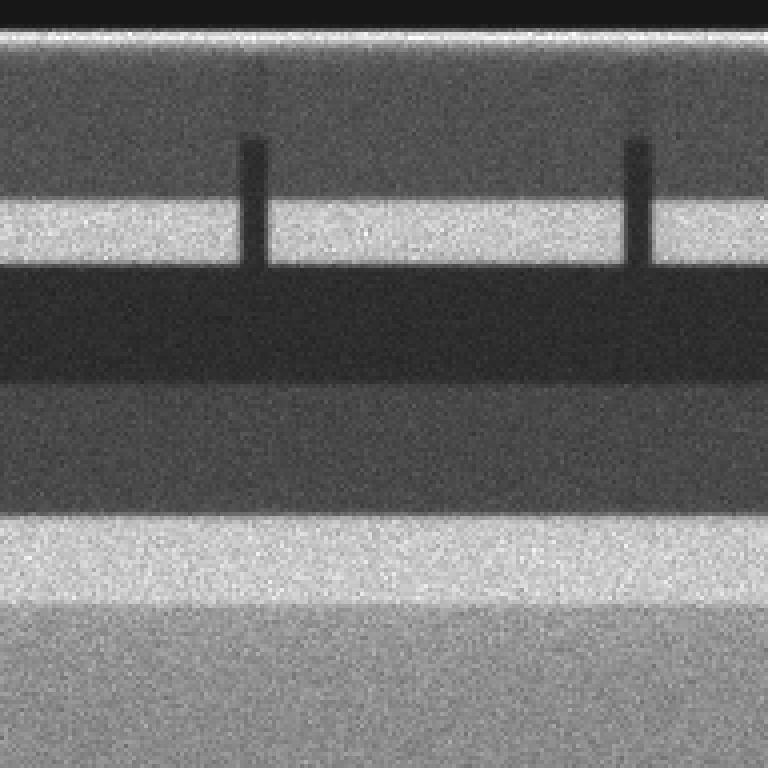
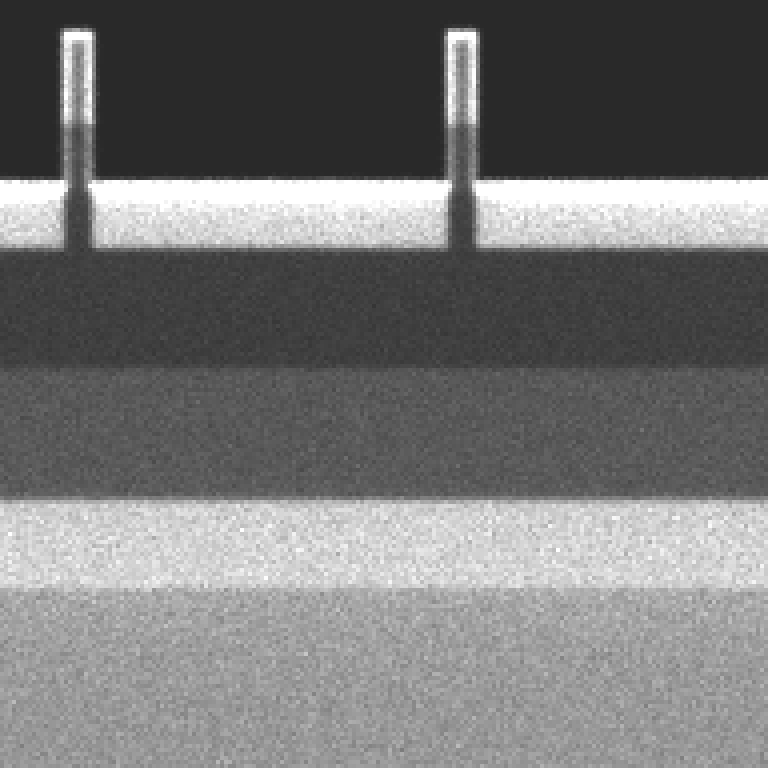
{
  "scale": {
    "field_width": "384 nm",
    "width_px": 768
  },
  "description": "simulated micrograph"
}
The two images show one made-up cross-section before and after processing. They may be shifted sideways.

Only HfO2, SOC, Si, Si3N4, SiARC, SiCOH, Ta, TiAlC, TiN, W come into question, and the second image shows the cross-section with SOC removed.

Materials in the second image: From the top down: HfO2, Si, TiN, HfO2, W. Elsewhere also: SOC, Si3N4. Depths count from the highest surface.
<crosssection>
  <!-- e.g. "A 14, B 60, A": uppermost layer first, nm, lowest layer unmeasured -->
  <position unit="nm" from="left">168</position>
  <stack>empty 76, HfO2 32, Si 60, TiN 66, HfO2 44, W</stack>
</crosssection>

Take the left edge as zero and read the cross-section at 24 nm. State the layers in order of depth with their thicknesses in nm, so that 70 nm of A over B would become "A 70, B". empty 76, HfO2 32, Si 60, TiN 66, HfO2 44, W